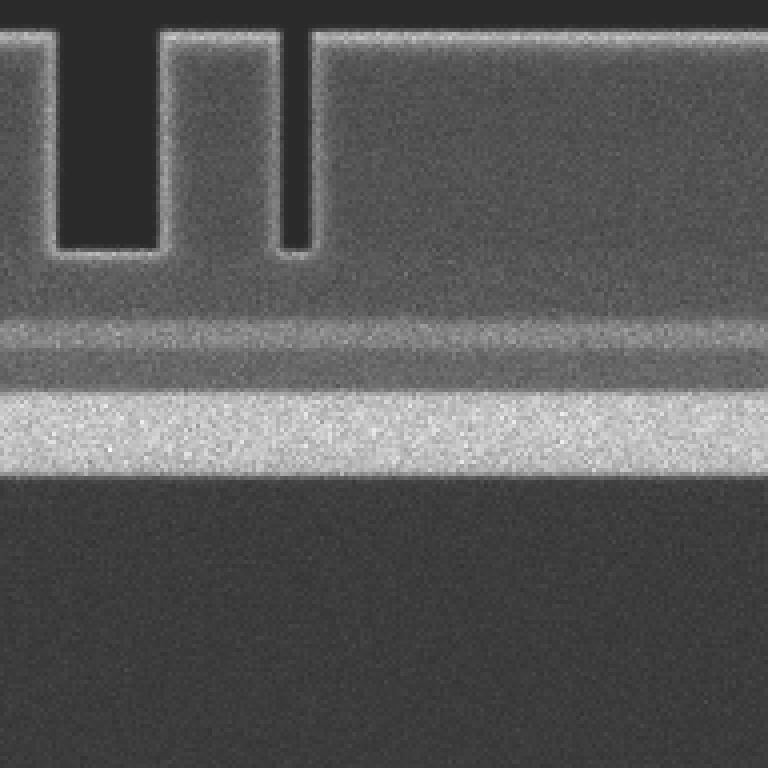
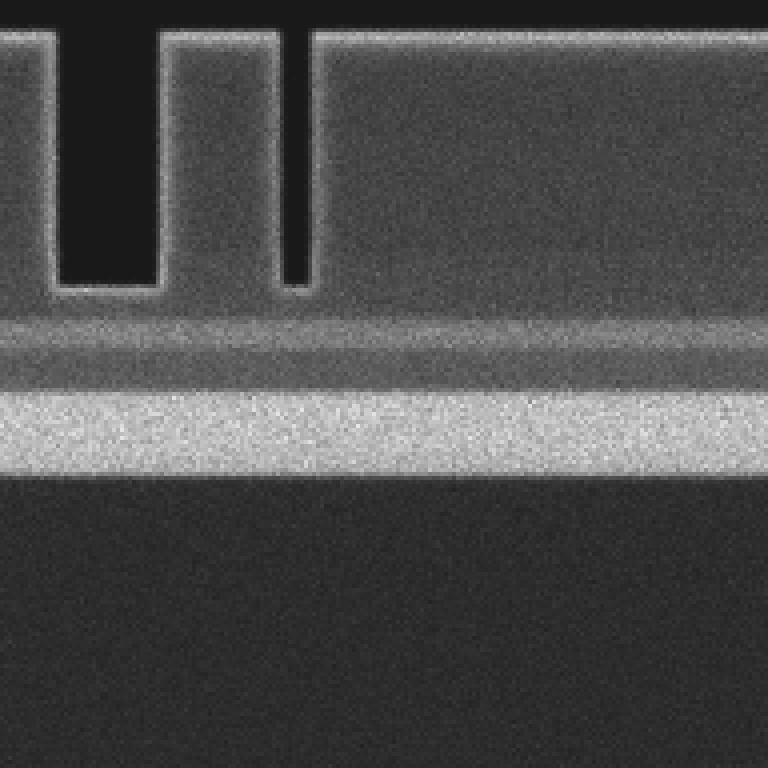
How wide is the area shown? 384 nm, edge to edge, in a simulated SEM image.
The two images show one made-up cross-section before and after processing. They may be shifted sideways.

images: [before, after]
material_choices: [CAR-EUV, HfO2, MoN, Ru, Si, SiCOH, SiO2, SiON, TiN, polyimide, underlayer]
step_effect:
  removed: TiN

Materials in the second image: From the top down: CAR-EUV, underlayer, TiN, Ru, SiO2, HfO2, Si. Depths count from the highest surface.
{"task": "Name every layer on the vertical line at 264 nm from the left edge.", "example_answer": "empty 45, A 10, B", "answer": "CAR-EUV 54, underlayer 56, TiN 34, Ru 14, SiO2 22, HfO2 42, Si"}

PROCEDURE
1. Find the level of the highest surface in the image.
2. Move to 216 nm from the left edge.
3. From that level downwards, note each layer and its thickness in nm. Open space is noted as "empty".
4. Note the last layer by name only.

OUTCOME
CAR-EUV 54, underlayer 56, TiN 34, Ru 14, SiO2 22, HfO2 42, Si